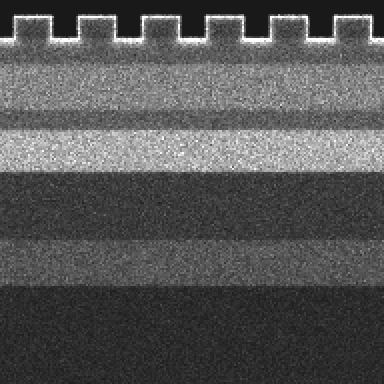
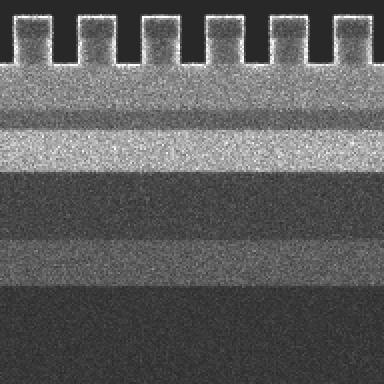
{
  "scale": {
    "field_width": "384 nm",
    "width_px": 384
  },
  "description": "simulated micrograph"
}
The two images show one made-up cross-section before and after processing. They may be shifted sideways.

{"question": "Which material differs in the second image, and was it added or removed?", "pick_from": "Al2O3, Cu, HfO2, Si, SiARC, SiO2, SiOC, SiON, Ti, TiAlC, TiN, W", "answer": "SiO2, removed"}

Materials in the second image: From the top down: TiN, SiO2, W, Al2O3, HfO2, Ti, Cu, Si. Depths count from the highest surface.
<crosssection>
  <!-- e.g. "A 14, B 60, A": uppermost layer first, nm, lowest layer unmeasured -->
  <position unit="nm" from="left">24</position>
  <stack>TiN 22, SiO2 26, W 46, Al2O3 20, HfO2 42, Ti 68, Cu 46, Si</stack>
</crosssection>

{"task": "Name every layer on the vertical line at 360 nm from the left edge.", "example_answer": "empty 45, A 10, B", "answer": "TiN 22, SiO2 26, W 46, Al2O3 20, HfO2 42, Ti 68, Cu 46, Si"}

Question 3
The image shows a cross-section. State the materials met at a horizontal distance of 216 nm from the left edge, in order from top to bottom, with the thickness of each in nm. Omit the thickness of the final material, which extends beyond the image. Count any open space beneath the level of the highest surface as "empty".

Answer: TiN 22, SiO2 26, W 46, Al2O3 20, HfO2 42, Ti 68, Cu 46, Si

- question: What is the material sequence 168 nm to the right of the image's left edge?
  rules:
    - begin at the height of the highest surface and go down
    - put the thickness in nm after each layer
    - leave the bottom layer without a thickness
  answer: TiN 22, SiO2 26, W 46, Al2O3 20, HfO2 42, Ti 68, Cu 46, Si